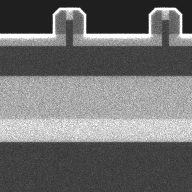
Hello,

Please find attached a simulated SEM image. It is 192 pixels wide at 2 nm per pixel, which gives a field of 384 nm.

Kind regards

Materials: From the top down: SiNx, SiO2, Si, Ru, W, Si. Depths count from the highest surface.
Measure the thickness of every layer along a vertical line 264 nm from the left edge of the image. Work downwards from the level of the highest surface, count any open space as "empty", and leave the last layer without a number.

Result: empty 52, SiO2 24, Si 60, Ru 86, W 46, Si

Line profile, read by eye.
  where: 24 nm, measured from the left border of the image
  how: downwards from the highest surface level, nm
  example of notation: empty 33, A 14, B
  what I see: empty 52, SiO2 24, Si 60, Ru 86, W 46, Si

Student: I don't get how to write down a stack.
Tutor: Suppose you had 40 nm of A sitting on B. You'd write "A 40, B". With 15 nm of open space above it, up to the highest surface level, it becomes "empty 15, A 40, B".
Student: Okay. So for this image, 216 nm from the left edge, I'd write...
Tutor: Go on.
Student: empty 52, SiO2 24, Si 60, Ru 86, W 46, Si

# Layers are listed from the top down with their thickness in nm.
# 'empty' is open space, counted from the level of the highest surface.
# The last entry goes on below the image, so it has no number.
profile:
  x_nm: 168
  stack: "empty 10, SiNx 42, SiO2 24, Si 60, Ru 86, W 46, Si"